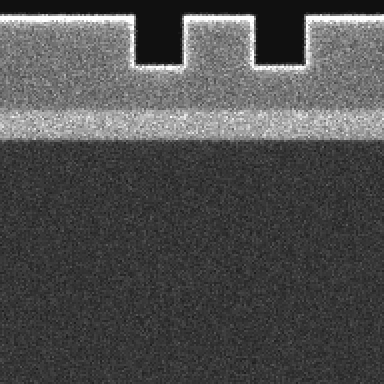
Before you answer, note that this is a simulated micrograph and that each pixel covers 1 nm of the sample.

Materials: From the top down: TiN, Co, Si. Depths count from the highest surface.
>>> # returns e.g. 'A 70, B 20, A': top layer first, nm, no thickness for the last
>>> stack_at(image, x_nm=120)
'TiN 94, Co 30, Si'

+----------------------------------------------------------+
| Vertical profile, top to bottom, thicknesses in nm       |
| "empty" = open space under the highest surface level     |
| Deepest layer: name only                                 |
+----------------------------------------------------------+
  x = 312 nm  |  TiN 94, Co 30, Si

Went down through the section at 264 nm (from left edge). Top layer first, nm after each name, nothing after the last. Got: empty 50, TiN 44, Co 30, Si